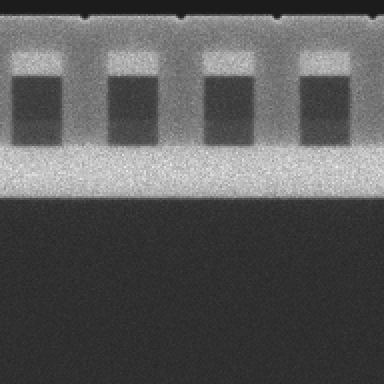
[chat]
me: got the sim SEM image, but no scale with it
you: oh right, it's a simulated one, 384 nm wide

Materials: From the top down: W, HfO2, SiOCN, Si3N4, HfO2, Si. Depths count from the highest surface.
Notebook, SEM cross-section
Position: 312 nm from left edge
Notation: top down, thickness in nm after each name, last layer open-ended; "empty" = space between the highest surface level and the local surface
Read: W 36, HfO2 24, SiOCN 44, Si3N4 26, HfO2 52, Si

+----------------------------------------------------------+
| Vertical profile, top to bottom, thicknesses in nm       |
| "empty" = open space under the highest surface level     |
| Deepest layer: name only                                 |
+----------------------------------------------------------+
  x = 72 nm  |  W 130, HfO2 52, Si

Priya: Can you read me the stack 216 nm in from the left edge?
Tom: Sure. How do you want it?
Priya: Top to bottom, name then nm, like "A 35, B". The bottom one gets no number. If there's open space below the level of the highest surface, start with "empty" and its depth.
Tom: W 36, HfO2 24, SiOCN 44, Si3N4 26, HfO2 52, Si